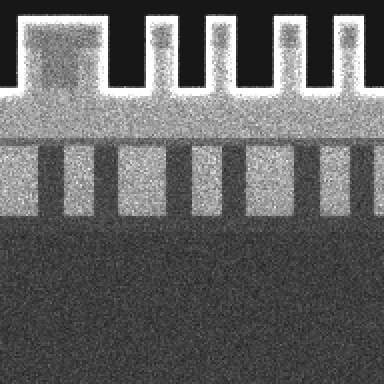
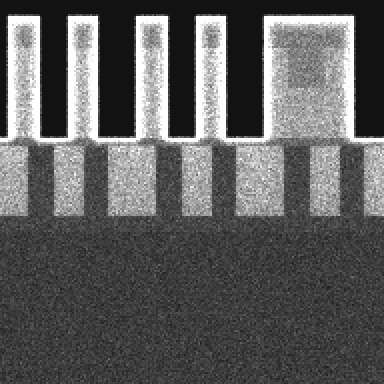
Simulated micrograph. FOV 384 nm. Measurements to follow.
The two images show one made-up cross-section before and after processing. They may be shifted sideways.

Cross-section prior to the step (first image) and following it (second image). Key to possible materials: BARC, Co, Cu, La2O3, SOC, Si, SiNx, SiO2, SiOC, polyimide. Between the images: SiO2 was removed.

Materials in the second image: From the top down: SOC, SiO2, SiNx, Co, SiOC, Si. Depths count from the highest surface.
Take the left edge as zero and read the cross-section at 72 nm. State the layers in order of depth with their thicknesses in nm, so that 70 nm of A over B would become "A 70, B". SOC 32, SiO2 90, SiNx 8, Co 70, SiOC 16, Si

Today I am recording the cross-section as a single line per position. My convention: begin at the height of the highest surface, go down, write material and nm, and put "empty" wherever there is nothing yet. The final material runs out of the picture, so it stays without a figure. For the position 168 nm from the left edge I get empty 122, SiNx 8, SiOC 86, Si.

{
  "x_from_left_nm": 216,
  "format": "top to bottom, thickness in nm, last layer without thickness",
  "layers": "SOC 32, SiO2 90, SiNx 8, SiOC 86, Si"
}